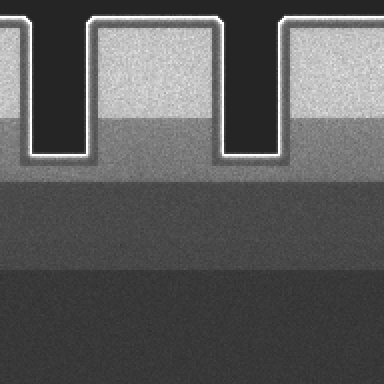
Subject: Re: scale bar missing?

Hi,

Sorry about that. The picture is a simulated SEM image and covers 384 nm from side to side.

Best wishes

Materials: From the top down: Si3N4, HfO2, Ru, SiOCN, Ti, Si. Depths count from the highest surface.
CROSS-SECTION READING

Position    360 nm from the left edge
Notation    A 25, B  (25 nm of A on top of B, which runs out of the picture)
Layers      Si3N4 12, HfO2 90, Ru 64, SiOCN 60, Ti 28, Si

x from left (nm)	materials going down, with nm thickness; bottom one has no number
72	empty 138, Si3N4 12, Ru 16, SiOCN 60, Ti 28, Si